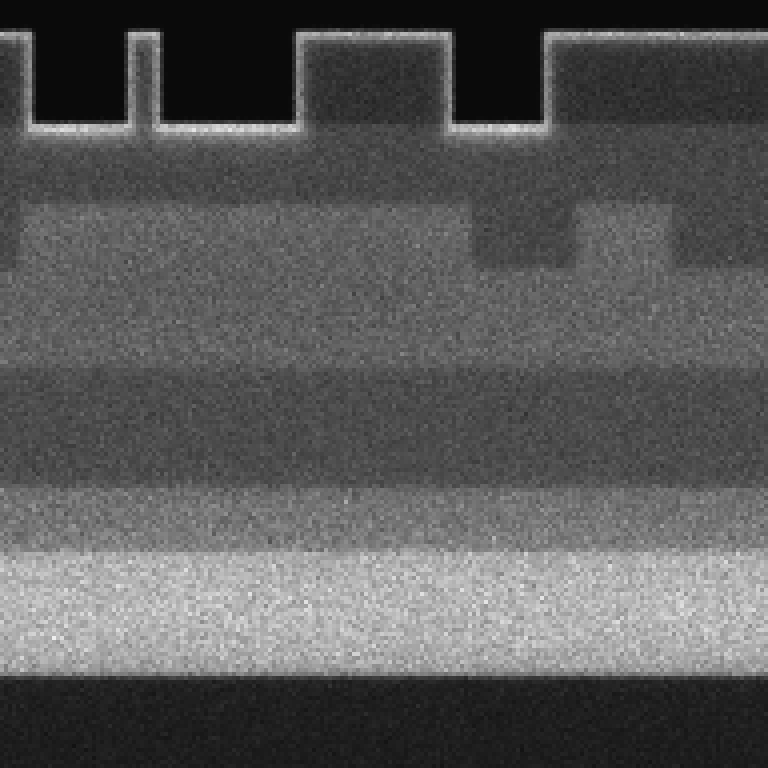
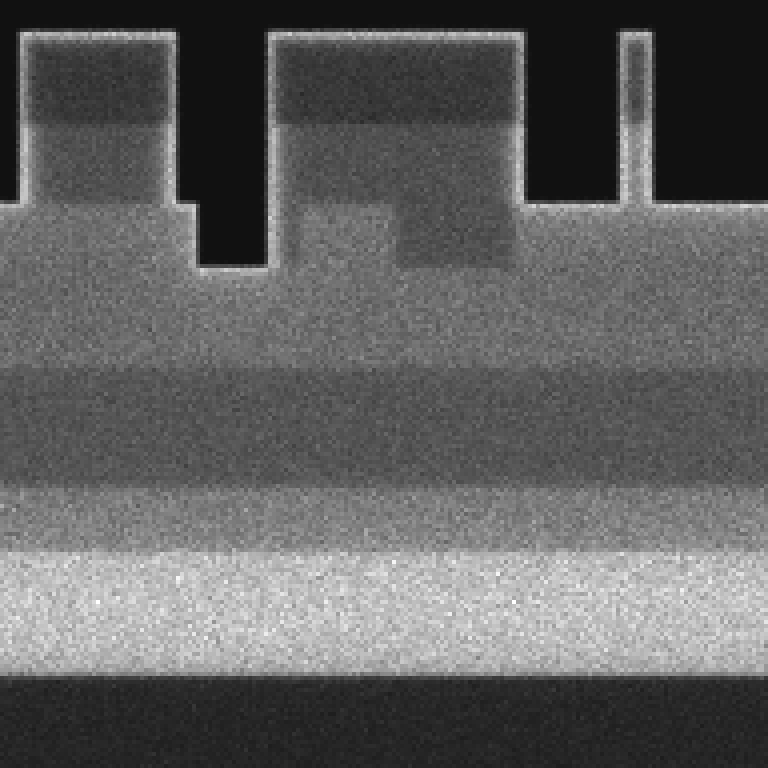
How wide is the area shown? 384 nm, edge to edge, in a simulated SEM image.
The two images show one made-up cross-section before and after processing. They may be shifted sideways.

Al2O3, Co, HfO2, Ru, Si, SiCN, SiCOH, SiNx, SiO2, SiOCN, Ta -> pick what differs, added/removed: SiO2 removed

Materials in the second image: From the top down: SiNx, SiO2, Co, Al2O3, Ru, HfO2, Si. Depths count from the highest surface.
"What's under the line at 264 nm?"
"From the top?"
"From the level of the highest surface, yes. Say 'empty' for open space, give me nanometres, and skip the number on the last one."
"empty 86, Co 82, Al2O3 60, Ru 32, HfO2 62, Si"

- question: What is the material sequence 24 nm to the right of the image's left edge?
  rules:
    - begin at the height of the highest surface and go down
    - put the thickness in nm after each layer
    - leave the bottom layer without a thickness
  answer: SiNx 46, SiO2 40, Co 82, Al2O3 60, Ru 32, HfO2 62, Si